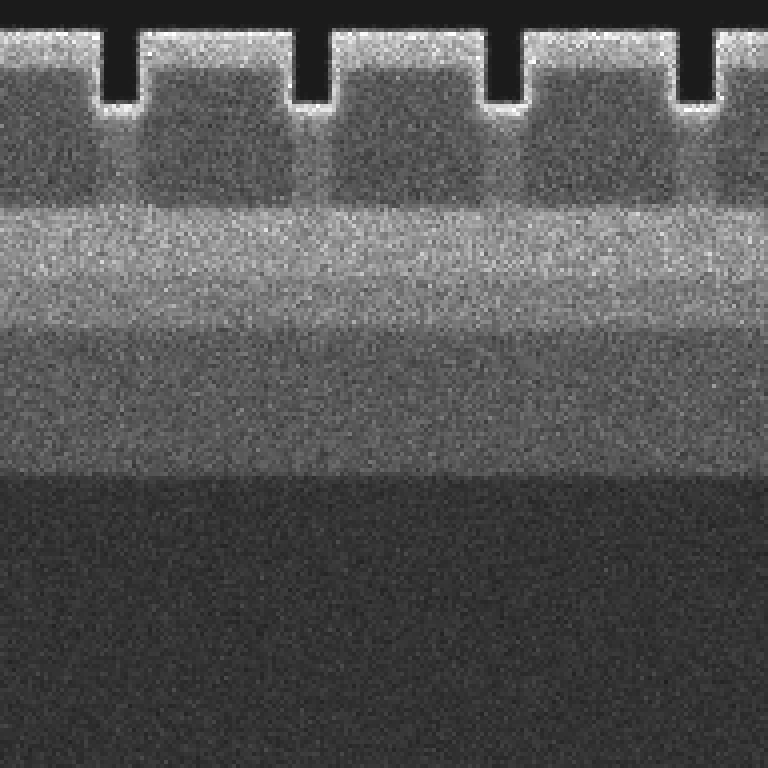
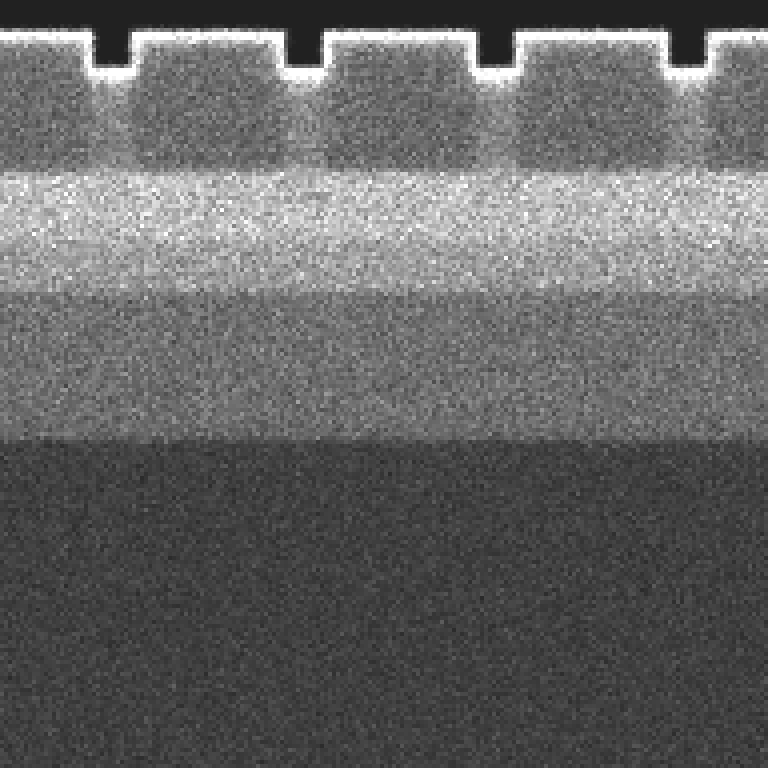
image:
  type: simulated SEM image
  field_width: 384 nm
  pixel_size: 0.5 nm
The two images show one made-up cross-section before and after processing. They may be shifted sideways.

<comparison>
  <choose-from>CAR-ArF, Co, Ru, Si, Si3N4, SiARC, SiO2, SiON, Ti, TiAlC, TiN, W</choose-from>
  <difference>Ru removed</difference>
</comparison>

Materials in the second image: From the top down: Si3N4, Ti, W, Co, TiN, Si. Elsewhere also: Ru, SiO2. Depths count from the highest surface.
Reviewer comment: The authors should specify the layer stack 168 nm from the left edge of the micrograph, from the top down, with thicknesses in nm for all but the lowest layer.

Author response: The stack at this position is Si3N4 42, Ti 28, W 34, Co 26, TiN 74, Si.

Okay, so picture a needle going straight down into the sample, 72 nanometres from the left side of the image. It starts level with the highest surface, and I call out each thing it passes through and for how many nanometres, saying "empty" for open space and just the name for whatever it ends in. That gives Si3N4 42, Ti 28, W 34, Co 26, TiN 74, Si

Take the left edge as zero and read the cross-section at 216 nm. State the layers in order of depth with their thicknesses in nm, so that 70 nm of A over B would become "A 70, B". Si3N4 42, Ti 28, W 34, Co 26, TiN 74, Si